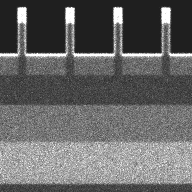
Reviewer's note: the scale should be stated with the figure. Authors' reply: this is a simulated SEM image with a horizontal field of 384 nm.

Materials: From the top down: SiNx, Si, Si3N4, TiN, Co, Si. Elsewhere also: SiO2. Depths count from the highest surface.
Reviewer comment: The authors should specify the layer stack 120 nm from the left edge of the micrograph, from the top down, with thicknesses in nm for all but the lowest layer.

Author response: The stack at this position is empty 92, SiNx 42, Si 60, Si3N4 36, TiN 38, Co 84, Si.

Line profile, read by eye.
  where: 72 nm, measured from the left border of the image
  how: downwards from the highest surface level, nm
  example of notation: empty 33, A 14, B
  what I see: empty 92, SiNx 42, Si 60, Si3N4 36, TiN 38, Co 84, Si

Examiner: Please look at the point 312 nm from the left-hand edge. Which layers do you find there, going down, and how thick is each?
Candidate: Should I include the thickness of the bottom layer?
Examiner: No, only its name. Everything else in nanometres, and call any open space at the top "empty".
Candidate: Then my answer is empty 92, SiNx 42, Si 60, Si3N4 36, TiN 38, Co 84, Si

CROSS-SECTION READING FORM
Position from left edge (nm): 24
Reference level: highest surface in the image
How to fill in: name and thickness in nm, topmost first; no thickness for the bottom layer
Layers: empty 92, SiNx 42, Si 60, Si3N4 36, TiN 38, Co 84, Si